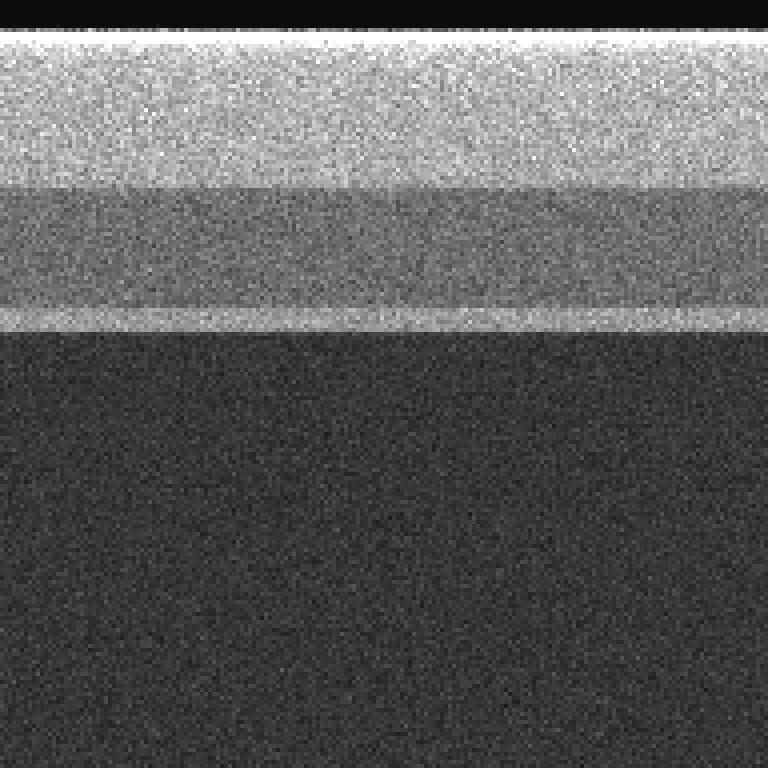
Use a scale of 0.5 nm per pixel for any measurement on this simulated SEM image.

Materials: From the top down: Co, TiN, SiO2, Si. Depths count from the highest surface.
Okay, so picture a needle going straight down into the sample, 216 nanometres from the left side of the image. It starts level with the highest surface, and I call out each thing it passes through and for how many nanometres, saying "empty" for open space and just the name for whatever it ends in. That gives Co 78, TiN 60, SiO2 12, Si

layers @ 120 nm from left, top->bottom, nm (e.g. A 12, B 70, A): Co 78, TiN 60, SiO2 12, Si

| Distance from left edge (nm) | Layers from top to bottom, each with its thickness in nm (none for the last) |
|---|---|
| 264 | Co 78, TiN 60, SiO2 12, Si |